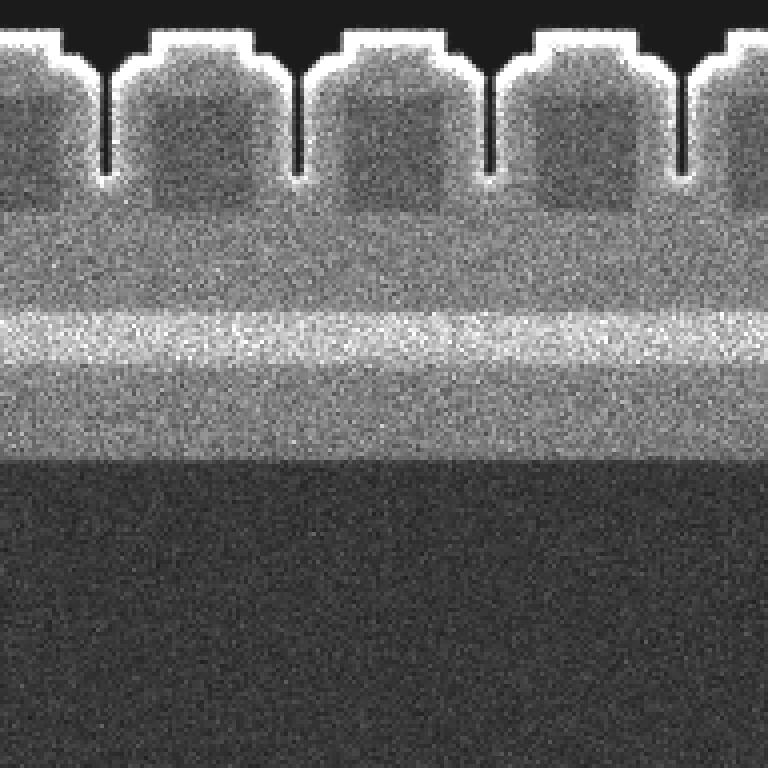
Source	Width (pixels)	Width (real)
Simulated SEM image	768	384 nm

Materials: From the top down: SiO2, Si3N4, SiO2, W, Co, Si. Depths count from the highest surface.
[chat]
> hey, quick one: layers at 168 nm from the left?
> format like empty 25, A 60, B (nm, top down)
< empty 12, SiO2 128, W 26, Co 48, Si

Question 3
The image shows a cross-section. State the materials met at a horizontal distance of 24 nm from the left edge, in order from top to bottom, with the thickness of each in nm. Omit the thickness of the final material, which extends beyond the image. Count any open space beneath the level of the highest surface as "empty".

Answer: SiO2 32, Si3N4 58, SiO2 50, W 26, Co 48, Si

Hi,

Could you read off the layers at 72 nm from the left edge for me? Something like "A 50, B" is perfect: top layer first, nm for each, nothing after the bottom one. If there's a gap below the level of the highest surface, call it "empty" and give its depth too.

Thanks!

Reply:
empty 12, SiO2 128, W 26, Co 48, Si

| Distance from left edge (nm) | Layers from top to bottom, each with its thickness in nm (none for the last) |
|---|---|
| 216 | SiO2 32, Si3N4 58, SiO2 50, W 26, Co 48, Si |